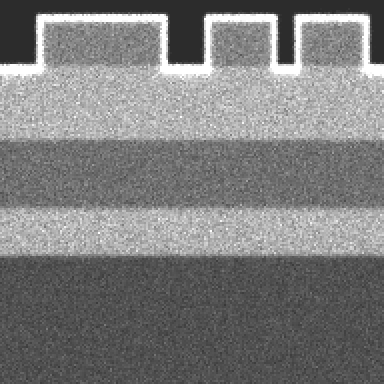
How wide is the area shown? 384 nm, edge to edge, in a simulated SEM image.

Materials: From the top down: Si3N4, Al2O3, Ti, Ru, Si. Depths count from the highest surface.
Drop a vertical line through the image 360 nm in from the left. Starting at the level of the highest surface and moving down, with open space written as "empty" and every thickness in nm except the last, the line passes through Si3N4 50, Al2O3 74, Ti 68, Ru 48, Si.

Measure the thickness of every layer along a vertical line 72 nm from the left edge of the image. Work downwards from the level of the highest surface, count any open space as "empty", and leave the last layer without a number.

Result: Si3N4 50, Al2O3 74, Ti 68, Ru 48, Si